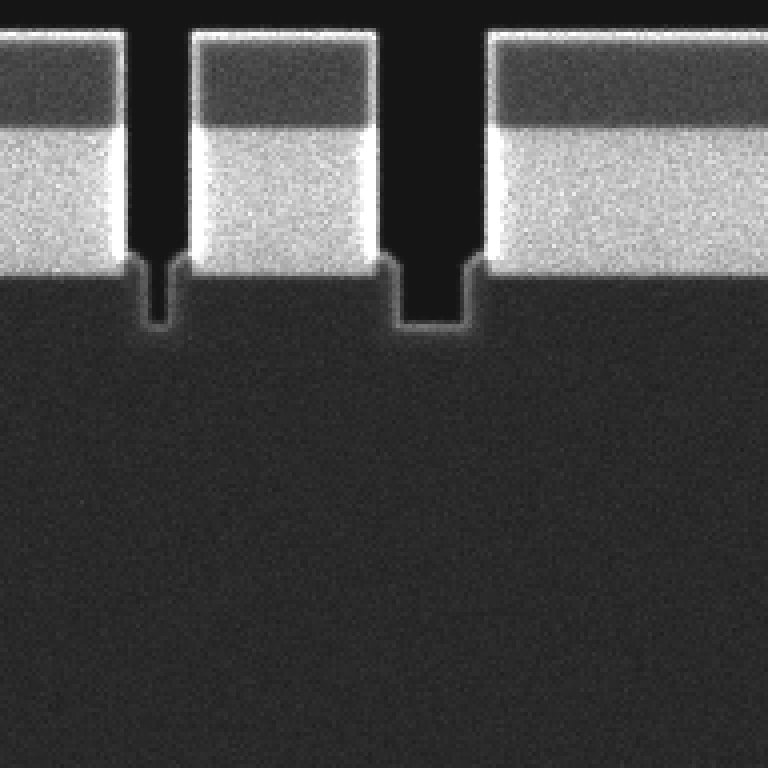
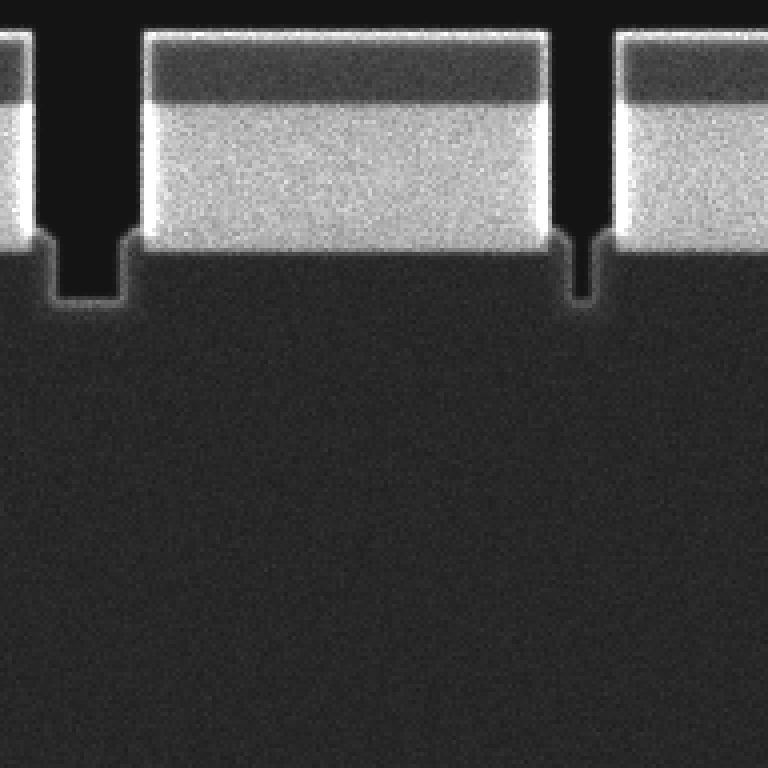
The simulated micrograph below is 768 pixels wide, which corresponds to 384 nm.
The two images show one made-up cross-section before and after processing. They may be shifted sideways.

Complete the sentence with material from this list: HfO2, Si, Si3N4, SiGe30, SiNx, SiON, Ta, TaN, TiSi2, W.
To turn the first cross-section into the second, Si3N4 must be removed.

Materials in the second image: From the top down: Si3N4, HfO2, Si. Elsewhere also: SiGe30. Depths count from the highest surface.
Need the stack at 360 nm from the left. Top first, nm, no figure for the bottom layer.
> Si3N4 36, HfO2 74, Si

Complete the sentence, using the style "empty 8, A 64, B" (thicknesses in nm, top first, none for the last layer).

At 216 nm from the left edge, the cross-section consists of Si3N4 36, HfO2 74, Si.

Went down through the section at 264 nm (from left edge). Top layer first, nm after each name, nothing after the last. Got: Si3N4 36, HfO2 74, Si